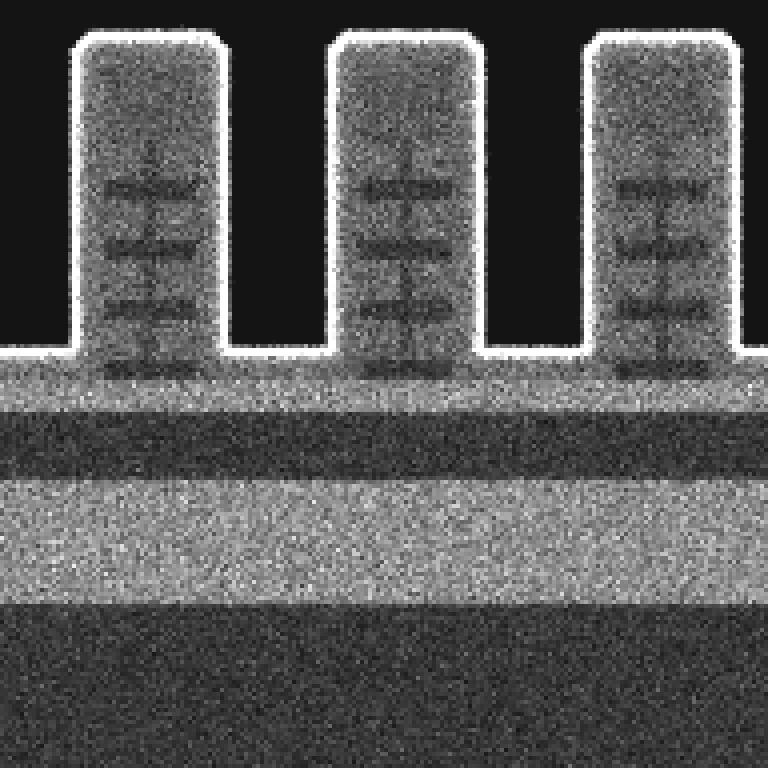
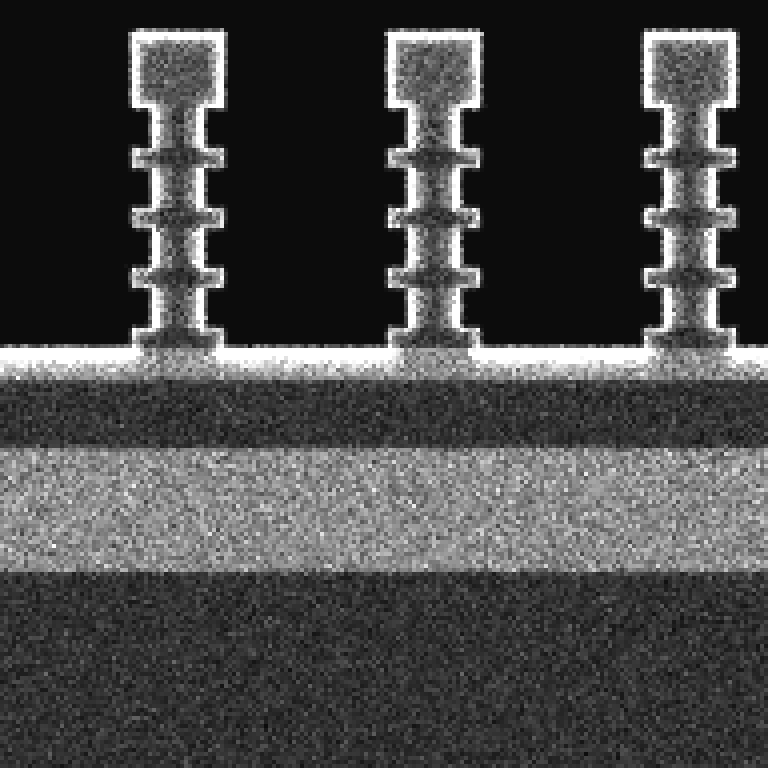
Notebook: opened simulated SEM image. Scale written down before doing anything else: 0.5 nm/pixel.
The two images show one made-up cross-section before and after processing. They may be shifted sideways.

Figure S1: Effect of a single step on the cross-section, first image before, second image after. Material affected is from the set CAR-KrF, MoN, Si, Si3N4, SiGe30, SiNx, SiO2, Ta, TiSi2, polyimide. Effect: removed Si3N4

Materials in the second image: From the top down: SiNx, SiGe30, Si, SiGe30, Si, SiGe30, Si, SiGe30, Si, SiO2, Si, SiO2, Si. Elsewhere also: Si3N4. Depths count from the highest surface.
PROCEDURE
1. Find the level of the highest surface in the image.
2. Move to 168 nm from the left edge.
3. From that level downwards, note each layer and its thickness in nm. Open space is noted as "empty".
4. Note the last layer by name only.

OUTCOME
empty 158, SiO2 16, Si 34, SiO2 62, Si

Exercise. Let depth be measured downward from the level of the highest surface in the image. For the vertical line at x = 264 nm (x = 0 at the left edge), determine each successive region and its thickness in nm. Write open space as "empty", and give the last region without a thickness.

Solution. empty 158, SiO2 16, Si 34, SiO2 62, Si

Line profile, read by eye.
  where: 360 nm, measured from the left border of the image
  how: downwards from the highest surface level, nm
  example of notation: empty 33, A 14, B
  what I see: SiNx 38, empty 20, Si 10, empty 20, Si 10, empty 20, Si 10, empty 20, Si 10, SiO2 16, Si 34, SiO2 62, Si